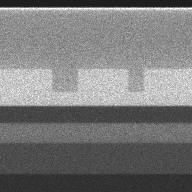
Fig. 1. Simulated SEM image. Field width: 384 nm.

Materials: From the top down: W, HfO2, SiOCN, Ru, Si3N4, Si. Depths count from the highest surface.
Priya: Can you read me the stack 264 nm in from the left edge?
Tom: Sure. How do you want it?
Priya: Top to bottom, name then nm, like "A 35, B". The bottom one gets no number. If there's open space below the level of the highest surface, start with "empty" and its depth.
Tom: W 168, HfO2 28, SiOCN 34, Ru 40, Si3N4 62, Si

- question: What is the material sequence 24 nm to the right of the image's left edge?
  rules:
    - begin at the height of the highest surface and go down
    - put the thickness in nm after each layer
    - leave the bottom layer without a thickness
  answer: W 122, HfO2 74, SiOCN 34, Ru 40, Si3N4 62, Si